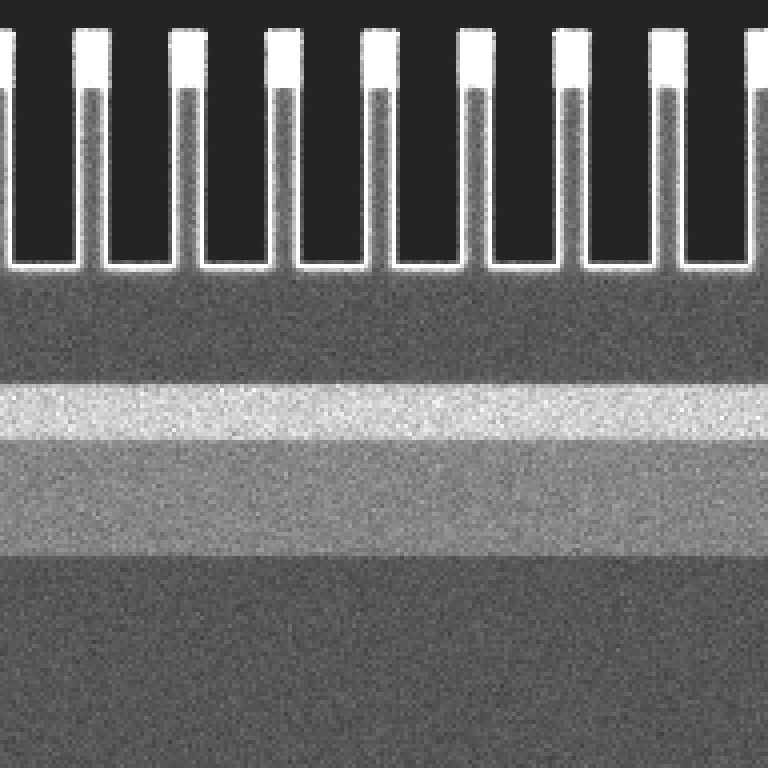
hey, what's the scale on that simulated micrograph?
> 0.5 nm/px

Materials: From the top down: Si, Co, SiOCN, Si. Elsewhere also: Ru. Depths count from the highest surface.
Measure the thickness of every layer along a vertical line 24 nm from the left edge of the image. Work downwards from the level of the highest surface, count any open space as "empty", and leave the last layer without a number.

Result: empty 116, Si 60, Co 28, SiOCN 58, Si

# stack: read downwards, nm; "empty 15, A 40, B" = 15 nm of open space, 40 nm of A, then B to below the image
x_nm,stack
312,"empty 116, Si 60, Co 28, SiOCN 58, Si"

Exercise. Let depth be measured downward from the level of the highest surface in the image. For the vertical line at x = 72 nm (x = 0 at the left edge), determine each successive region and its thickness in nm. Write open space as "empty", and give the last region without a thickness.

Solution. empty 116, Si 60, Co 28, SiOCN 58, Si